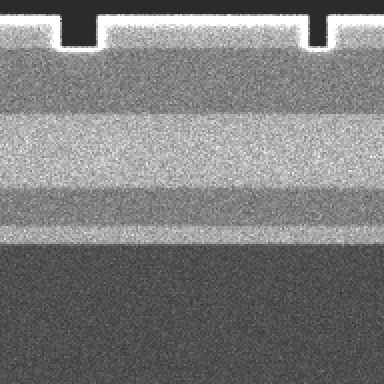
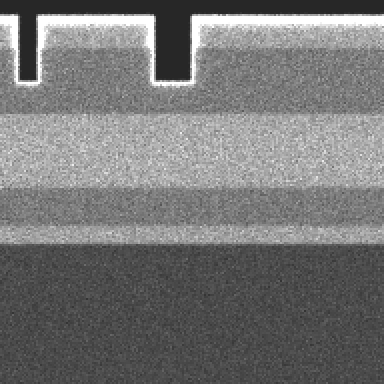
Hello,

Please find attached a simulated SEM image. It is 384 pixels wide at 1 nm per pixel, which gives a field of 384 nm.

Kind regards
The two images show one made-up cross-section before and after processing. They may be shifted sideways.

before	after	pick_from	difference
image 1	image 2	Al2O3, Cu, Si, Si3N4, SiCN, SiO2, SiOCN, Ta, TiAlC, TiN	TiN removed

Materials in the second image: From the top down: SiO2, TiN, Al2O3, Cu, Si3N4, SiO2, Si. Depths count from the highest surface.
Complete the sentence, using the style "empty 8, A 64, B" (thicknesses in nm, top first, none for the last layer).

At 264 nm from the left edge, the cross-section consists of SiO2 32, TiN 66, Al2O3 18, Cu 56, Si3N4 38, SiO2 18, Si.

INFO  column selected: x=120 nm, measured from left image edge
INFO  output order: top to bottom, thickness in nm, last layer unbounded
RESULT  SiO2 32, TiN 66, Al2O3 18, Cu 56, Si3N4 38, SiO2 18, Si